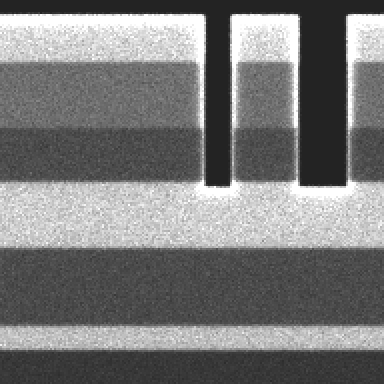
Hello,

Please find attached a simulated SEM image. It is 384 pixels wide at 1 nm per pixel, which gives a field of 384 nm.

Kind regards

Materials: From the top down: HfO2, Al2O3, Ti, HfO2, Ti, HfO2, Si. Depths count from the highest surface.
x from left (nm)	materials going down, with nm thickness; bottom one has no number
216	empty 172, HfO2 60, Ti 78, HfO2 24, Si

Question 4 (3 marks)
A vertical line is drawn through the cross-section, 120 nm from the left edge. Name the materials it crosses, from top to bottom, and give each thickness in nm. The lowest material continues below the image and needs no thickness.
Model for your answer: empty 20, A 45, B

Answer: HfO2 46, Al2O3 66, Ti 54, HfO2 66, Ti 78, HfO2 24, Si